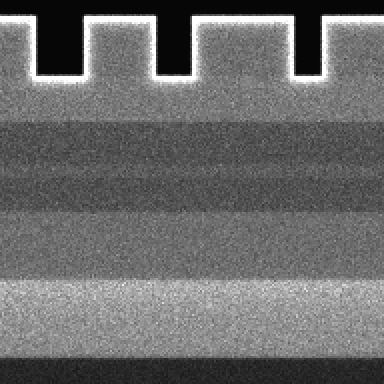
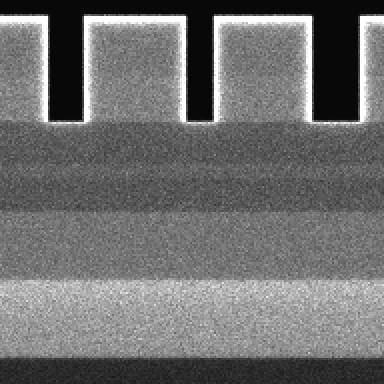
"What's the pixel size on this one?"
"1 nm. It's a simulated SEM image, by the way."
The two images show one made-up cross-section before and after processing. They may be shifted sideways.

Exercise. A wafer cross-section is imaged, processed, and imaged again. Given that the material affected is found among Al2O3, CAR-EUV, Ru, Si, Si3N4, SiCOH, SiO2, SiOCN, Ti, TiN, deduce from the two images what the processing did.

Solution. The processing removed Al2O3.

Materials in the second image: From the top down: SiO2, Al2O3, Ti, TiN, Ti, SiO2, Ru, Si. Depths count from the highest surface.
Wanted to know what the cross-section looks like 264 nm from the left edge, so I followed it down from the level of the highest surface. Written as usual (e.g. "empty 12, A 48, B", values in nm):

SiO2 60, Al2O3 46, Ti 42, TiN 14, Ti 34, SiO2 68, Ru 78, Si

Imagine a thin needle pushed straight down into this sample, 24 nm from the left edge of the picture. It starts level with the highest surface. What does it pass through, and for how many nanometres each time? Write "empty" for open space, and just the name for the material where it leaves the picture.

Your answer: SiO2 60, Al2O3 46, Ti 42, TiN 14, Ti 34, SiO2 68, Ru 78, Si